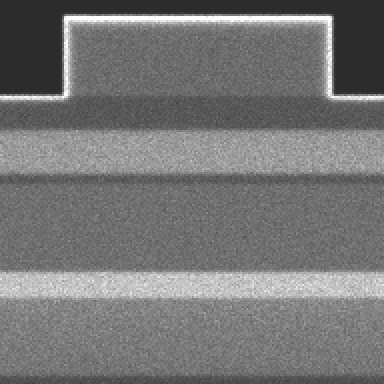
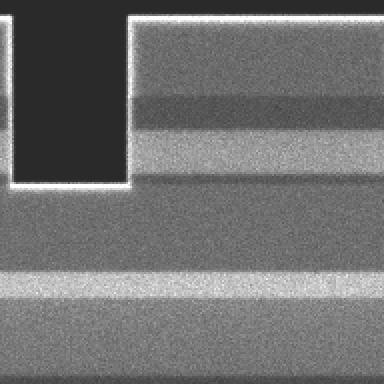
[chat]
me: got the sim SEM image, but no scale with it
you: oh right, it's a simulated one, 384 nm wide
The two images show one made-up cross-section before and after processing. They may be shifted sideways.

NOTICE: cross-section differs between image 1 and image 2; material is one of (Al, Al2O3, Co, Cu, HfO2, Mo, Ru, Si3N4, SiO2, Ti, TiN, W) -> removed: Si3N4 and TiN and W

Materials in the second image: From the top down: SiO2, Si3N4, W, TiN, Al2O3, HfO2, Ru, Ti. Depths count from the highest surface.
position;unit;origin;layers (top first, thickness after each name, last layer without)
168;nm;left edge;SiO2 80, Si3N4 34, W 44, TiN 10, Al2O3 88, HfO2 26, Ru 78, Ti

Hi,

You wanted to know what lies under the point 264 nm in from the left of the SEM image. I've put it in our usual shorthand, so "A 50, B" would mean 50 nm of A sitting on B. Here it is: SiO2 80, Si3N4 34, W 44, TiN 10, Al2O3 88, HfO2 26, Ru 78, Ti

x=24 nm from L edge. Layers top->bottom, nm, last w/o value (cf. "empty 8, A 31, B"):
empty 168, Al2O3 88, HfO2 26, Ru 78, Ti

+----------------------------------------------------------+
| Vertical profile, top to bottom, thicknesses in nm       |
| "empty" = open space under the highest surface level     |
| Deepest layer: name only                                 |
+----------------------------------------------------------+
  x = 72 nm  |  empty 168, Al2O3 88, HfO2 26, Ru 78, Ti